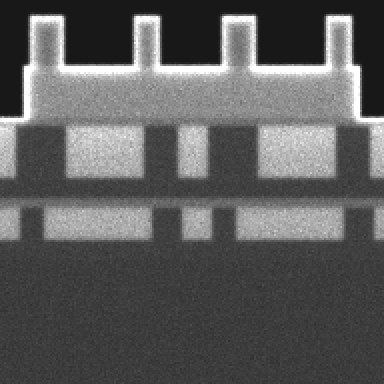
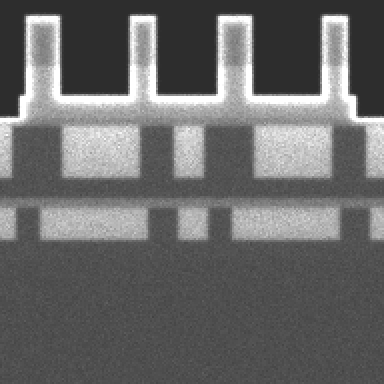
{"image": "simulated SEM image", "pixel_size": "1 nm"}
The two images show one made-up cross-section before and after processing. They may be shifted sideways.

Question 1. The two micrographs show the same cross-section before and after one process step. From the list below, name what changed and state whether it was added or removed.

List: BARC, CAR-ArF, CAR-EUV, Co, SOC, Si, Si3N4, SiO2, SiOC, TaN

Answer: SiO2, removed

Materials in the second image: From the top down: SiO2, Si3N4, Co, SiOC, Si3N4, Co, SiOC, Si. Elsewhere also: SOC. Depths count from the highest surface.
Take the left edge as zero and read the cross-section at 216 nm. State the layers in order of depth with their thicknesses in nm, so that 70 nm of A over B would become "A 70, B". empty 80, SiO2 22, Si3N4 8, SiOC 72, Si3N4 10, SiOC 52, Si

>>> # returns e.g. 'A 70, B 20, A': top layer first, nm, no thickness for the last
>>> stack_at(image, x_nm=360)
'empty 102, Si3N4 8, SiOC 72, Si3N4 10, SiOC 52, Si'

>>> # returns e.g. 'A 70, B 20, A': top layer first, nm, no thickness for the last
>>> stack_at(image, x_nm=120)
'empty 80, SiO2 22, Si3N4 8, Co 52, SiOC 20, Si3N4 10, Co 32, SiOC 20, Si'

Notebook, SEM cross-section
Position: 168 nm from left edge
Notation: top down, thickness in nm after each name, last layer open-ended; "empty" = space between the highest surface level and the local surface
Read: empty 80, SiO2 22, Si3N4 8, SiOC 72, Si3N4 10, SiOC 52, Si